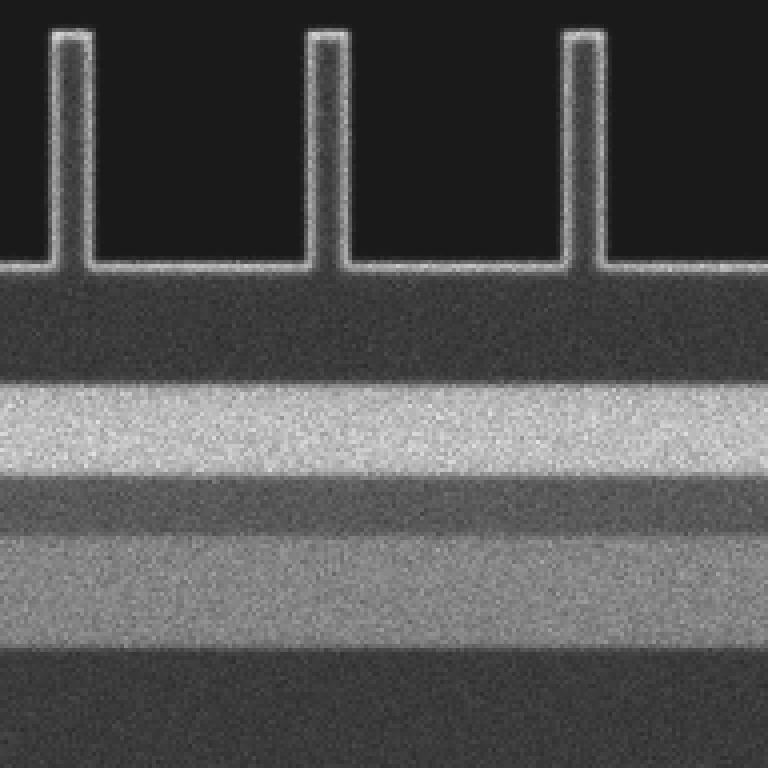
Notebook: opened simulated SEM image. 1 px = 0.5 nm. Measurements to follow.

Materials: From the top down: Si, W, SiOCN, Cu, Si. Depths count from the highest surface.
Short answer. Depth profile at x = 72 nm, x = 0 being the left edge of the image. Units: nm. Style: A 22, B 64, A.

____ empty 116, Si 60, W 46, SiOCN 30, Cu 56, Si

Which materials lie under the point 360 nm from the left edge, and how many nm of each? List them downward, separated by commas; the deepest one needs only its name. empty 116, Si 60, W 46, SiOCN 30, Cu 56, Si